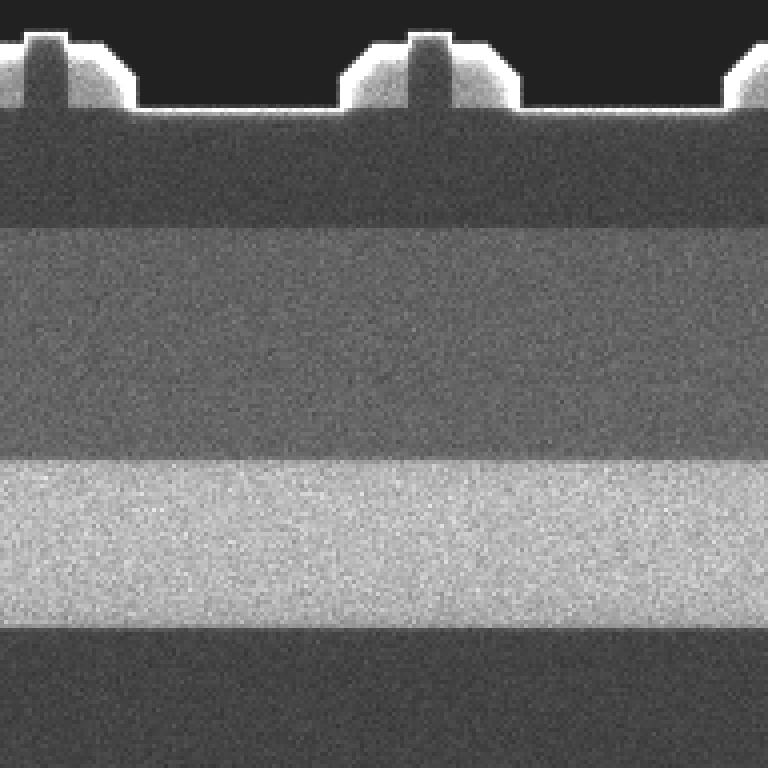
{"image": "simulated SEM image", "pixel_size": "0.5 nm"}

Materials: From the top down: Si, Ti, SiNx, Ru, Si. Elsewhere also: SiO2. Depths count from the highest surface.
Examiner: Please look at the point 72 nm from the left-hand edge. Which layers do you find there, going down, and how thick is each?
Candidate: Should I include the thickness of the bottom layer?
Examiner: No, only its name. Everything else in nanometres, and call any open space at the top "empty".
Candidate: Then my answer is empty 38, Si 60, Ti 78, SiNx 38, Ru 84, Si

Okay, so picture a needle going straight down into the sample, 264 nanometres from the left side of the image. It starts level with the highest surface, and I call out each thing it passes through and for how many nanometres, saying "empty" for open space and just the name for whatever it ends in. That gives empty 38, Si 60, Ti 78, SiNx 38, Ru 84, Si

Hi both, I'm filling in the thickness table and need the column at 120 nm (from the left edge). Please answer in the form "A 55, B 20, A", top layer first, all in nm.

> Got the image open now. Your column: empty 38, Si 60, Ti 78, SiNx 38, Ru 84, Si